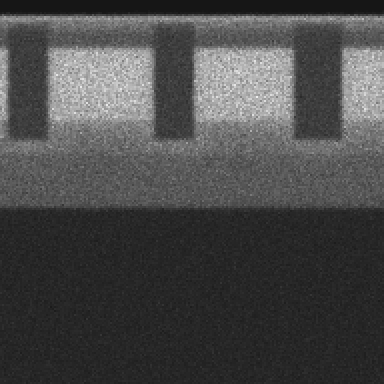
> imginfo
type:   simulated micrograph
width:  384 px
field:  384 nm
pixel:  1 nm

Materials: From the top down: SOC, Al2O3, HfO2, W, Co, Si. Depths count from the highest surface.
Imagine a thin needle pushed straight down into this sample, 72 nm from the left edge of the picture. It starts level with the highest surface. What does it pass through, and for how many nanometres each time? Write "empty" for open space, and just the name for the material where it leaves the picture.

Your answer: SOC 8, Al2O3 24, HfO2 72, W 34, Co 54, Si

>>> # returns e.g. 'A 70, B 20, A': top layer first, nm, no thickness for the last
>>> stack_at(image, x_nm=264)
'SOC 8, Al2O3 24, HfO2 72, W 34, Co 54, Si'